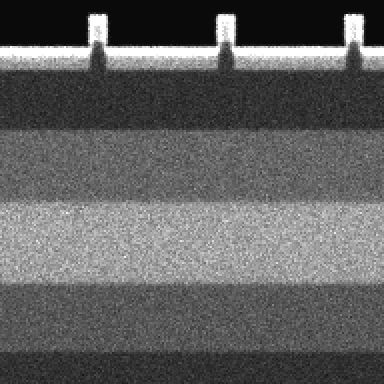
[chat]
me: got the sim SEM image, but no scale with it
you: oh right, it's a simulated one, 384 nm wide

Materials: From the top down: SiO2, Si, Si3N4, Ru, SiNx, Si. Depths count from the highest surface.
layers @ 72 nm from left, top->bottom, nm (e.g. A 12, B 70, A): empty 32, SiO2 22, Si 60, Si3N4 72, Ru 82, SiNx 68, Si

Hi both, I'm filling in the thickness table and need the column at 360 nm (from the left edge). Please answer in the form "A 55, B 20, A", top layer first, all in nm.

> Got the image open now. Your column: Ru 26, Si 88, Si3N4 72, Ru 82, SiNx 68, Si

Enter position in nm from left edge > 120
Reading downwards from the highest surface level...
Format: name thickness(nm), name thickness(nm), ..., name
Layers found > empty 32, SiO2 22, Si 60, Si3N4 72, Ru 82, SiNx 68, Si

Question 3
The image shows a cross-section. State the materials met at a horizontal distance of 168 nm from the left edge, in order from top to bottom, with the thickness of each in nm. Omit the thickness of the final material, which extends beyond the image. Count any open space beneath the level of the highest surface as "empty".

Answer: empty 32, SiO2 22, Si 60, Si3N4 72, Ru 82, SiNx 68, Si